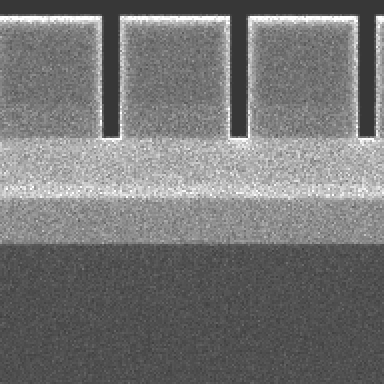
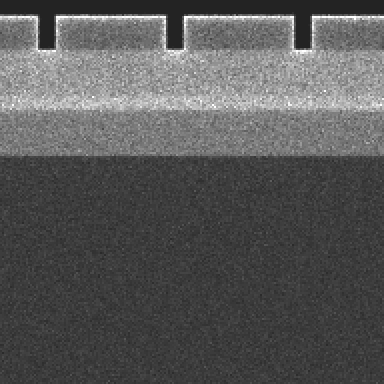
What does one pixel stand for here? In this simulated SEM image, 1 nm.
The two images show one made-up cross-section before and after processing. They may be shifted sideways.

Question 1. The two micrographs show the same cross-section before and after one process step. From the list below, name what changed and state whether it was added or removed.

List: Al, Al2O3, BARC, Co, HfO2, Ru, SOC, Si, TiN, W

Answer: SOC, removed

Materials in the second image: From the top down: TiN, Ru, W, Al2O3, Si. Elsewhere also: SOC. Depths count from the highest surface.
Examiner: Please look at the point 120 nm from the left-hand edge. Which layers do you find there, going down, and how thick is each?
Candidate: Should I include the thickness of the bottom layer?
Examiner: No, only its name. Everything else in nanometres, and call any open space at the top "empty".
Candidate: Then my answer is TiN 34, Ru 46, W 14, Al2O3 46, Si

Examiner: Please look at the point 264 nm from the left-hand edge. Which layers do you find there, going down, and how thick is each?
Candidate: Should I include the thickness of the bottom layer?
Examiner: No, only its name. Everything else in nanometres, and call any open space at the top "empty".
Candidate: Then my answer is TiN 34, Ru 46, W 14, Al2O3 46, Si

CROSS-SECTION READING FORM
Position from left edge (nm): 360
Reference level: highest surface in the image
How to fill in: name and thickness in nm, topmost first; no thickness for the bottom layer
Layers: TiN 34, Ru 46, W 14, Al2O3 46, Si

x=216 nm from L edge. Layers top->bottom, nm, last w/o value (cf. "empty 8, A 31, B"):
TiN 34, Ru 46, W 14, Al2O3 46, Si